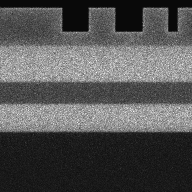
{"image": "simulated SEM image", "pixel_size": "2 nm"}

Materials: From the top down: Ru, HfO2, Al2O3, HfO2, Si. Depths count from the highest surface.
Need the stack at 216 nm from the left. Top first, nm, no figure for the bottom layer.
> Ru 76, HfO2 72, Al2O3 44, HfO2 56, Si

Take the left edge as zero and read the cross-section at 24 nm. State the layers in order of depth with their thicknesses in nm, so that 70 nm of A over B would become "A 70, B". Ru 76, HfO2 72, Al2O3 44, HfO2 56, Si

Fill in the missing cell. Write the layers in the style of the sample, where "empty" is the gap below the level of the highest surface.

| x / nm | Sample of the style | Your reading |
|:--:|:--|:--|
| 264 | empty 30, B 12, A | empty 48, Ru 28, HfO2 72, Al2O3 44, HfO2 56, Si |